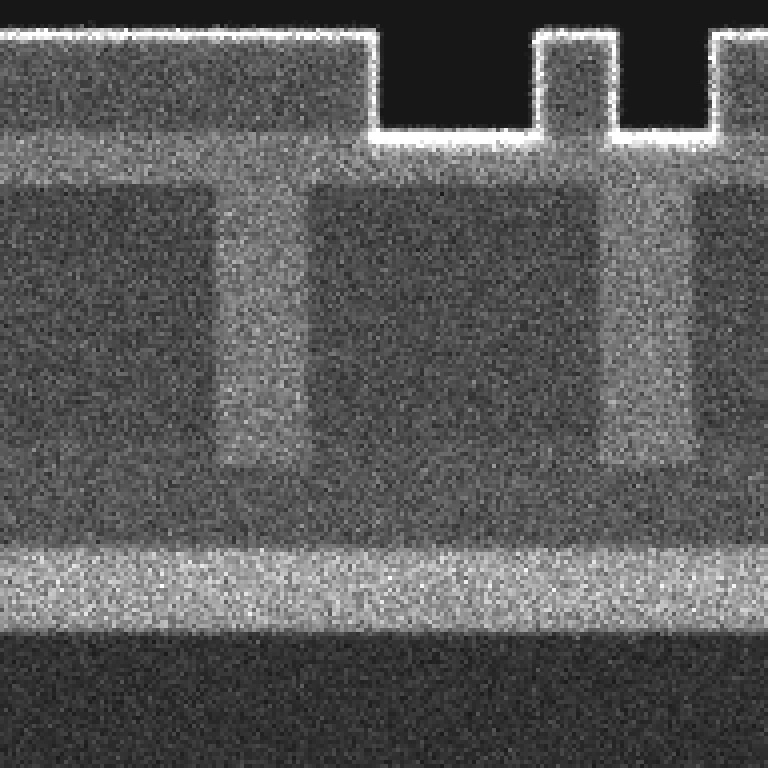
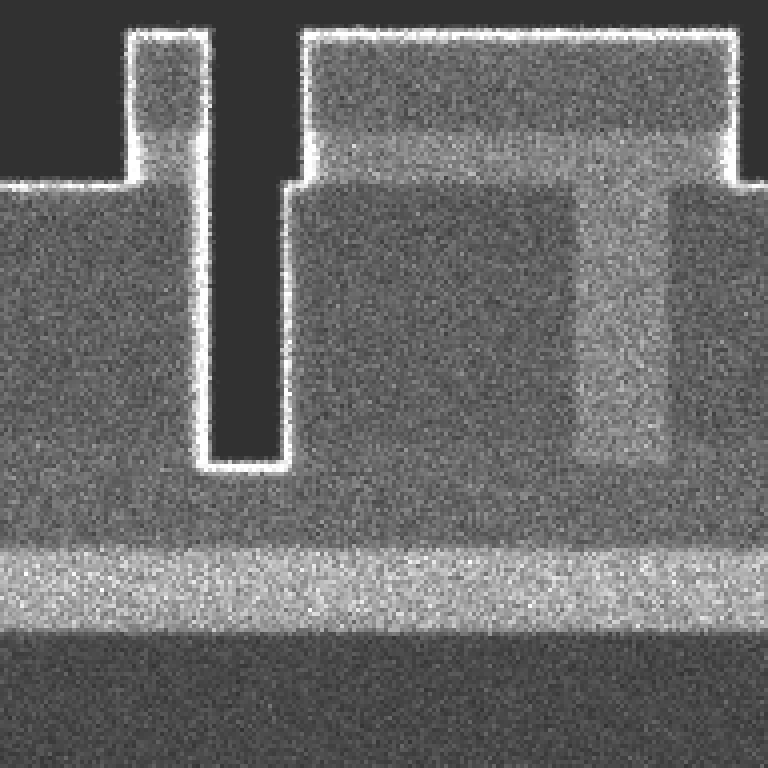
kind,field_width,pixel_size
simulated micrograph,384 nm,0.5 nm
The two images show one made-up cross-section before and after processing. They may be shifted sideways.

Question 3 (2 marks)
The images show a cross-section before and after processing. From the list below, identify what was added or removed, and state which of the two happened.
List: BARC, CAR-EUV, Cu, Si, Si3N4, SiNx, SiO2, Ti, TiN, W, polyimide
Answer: SiO2 was removed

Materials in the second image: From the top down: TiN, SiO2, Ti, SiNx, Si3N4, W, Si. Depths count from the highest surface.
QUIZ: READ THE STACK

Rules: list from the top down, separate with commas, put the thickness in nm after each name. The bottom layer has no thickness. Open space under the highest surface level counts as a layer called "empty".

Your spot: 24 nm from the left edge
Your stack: empty 76, Ti 38, SiNx 90, Si3N4 54, W 42, Si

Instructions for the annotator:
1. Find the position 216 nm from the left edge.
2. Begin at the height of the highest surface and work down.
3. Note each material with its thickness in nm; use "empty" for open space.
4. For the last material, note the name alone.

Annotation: TiN 50, SiO2 26, Ti 38, SiNx 90, Si3N4 54, W 42, Si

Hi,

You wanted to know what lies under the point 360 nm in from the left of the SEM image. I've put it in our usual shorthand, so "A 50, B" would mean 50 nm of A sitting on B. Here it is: TiN 50, SiO2 26, Ti 38, SiNx 90, Si3N4 54, W 42, Si